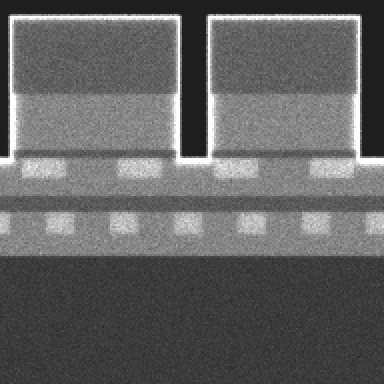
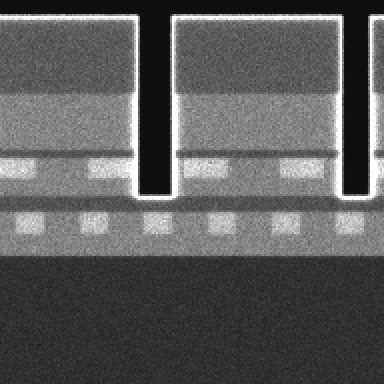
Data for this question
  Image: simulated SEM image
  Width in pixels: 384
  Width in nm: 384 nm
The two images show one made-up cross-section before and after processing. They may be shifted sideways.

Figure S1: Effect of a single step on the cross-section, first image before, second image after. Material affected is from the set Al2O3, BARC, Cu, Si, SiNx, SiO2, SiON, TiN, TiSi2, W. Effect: removed SiO2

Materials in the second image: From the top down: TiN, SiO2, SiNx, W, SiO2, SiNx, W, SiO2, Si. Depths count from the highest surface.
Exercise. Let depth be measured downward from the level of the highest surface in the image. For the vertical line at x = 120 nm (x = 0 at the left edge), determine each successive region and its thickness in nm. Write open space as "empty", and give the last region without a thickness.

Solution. TiN 78, SiO2 56, SiNx 8, W 20, SiO2 18, SiNx 16, SiO2 44, Si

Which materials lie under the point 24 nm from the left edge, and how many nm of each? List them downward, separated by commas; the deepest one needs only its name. TiN 78, SiO2 56, SiNx 8, W 20, SiO2 18, SiNx 16, W 22, SiO2 22, Si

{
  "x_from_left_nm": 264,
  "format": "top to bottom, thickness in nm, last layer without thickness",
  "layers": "TiN 78, SiO2 56, SiNx 8, SiO2 38, SiNx 16, SiO2 44, Si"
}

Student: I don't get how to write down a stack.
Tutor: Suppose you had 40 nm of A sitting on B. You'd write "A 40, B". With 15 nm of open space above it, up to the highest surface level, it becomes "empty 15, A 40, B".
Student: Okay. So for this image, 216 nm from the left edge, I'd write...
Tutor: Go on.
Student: TiN 78, SiO2 56, SiNx 8, W 20, SiO2 18, SiNx 16, W 22, SiO2 22, Si